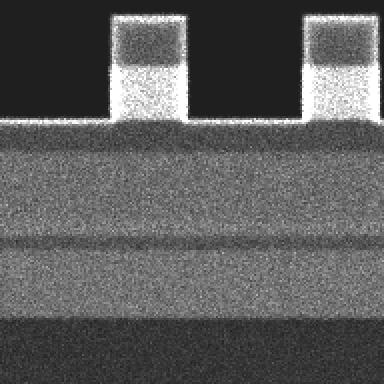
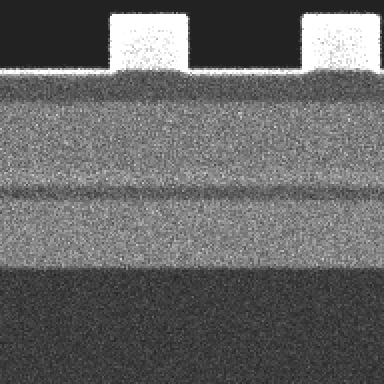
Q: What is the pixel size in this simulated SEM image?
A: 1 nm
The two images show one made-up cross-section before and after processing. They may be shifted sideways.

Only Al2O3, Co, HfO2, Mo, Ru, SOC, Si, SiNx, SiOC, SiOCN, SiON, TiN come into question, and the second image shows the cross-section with SOC removed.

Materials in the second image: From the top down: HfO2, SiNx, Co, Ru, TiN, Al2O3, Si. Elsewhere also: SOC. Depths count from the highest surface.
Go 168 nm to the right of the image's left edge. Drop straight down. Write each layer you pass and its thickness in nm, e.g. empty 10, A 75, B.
HfO2 54, SiNx 32, Co 68, Ru 16, TiN 14, Al2O3 68, Si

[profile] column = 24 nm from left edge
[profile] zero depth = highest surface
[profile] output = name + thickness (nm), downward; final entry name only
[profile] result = empty 54, SiNx 32, Co 68, Ru 16, TiN 14, Al2O3 68, Si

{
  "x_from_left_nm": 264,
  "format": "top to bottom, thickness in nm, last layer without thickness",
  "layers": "empty 54, SiNx 32, Co 68, Ru 16, TiN 14, Al2O3 68, Si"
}